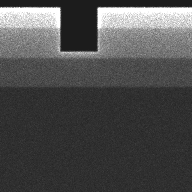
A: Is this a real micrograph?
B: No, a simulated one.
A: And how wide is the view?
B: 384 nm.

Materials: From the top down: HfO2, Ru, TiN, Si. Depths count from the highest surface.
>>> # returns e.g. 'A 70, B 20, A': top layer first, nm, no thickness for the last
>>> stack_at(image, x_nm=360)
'HfO2 40, Ru 60, TiN 58, Si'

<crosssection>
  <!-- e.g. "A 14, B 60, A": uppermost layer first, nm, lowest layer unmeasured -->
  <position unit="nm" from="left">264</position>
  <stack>HfO2 40, Ru 60, TiN 58, Si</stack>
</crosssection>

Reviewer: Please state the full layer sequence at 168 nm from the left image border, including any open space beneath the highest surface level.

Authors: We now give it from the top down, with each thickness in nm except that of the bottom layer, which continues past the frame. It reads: empty 88, Ru 12, TiN 58, Si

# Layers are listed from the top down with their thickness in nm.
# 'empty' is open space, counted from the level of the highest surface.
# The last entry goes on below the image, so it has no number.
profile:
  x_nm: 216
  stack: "HfO2 40, Ru 60, TiN 58, Si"